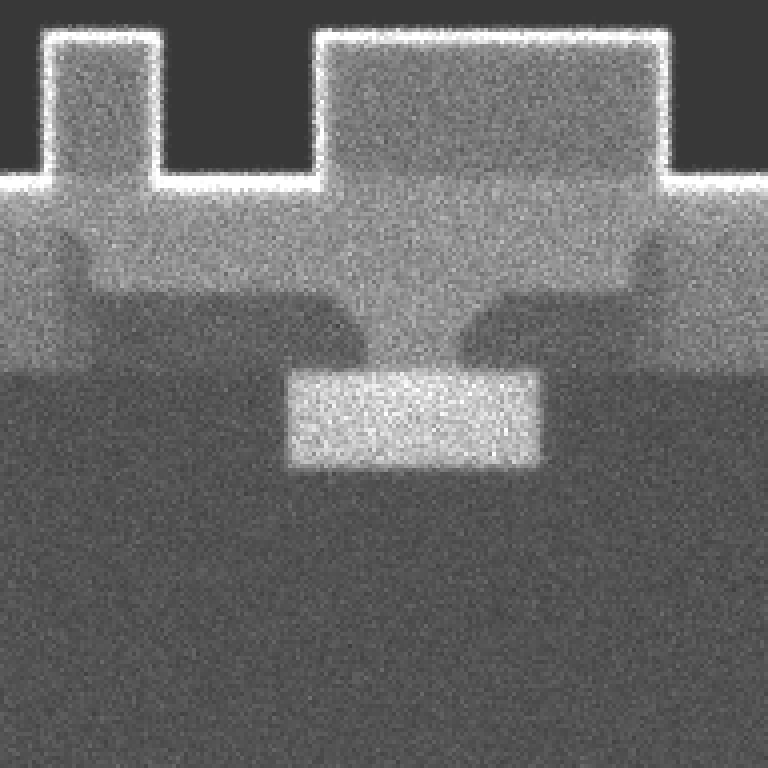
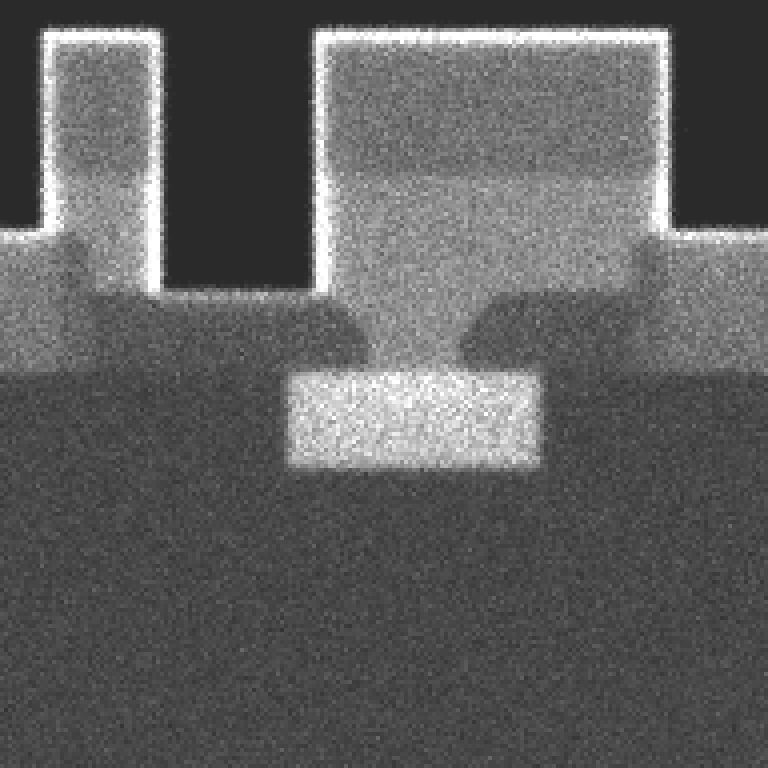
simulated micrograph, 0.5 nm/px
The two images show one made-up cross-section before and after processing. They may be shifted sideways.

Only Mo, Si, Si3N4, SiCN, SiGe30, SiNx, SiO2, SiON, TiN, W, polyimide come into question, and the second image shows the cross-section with SiO2 removed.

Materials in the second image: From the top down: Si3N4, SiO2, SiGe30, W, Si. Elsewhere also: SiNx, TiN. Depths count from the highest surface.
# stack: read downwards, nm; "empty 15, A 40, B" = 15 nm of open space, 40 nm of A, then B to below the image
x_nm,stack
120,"empty 130, SiGe30 40, Si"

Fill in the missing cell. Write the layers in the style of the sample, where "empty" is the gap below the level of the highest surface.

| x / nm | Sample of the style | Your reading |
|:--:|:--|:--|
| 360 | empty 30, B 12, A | empty 100, TiN 70, Si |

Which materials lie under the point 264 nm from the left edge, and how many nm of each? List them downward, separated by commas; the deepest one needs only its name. Si3N4 72, SiO2 58, SiGe30 40, W 48, Si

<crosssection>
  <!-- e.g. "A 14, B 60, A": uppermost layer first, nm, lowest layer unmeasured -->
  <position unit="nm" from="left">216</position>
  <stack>Si3N4 72, SiO2 98, W 48, Si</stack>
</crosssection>